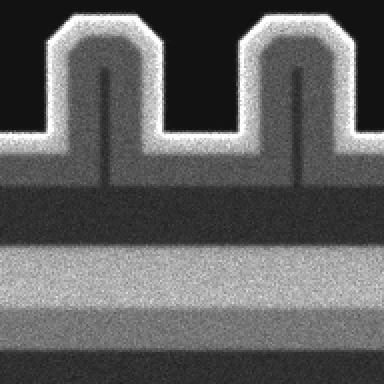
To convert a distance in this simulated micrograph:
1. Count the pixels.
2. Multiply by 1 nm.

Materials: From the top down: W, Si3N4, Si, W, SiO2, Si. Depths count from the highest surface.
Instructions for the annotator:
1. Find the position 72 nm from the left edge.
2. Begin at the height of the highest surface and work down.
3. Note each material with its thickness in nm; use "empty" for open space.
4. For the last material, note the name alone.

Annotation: empty 2, W 30, Si3N4 138, Si 60, W 62, SiO2 42, Si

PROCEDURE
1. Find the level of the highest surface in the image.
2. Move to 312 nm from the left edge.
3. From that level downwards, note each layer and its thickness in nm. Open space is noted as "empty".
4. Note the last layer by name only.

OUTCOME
W 20, Si3N4 150, Si 60, W 62, SiO2 42, Si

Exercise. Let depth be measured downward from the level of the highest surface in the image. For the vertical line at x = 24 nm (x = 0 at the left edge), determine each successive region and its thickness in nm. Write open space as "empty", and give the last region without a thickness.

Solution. empty 118, W 20, Si3N4 32, Si 60, W 62, SiO2 42, Si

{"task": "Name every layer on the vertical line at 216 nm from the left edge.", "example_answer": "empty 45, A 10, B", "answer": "empty 118, W 20, Si3N4 32, Si 60, W 62, SiO2 42, Si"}